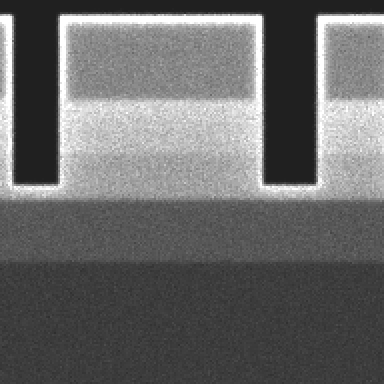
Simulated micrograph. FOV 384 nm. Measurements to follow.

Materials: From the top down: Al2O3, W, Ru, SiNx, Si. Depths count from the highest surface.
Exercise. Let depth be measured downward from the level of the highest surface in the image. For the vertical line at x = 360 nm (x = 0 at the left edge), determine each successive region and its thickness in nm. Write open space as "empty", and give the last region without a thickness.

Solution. Al2O3 84, W 54, Ru 46, SiNx 62, Si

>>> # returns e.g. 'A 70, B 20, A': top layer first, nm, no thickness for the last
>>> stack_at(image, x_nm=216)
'Al2O3 84, W 54, Ru 46, SiNx 62, Si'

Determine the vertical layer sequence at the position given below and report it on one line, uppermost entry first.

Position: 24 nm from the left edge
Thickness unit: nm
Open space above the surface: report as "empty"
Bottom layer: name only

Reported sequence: empty 170, Ru 14, SiNx 62, Si